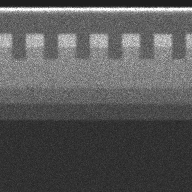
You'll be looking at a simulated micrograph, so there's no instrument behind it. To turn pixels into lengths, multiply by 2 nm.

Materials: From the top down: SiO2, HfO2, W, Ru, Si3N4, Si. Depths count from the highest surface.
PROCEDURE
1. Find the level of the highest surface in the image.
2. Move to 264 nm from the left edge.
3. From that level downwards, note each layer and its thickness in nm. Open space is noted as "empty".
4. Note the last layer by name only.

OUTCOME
SiO2 52, HfO2 26, W 82, Ru 32, Si3N4 32, Si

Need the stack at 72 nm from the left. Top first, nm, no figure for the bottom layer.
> SiO2 52, HfO2 26, W 82, Ru 32, Si3N4 32, Si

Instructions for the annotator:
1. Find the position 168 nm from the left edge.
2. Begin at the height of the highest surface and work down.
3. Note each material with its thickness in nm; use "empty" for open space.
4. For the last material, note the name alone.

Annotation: SiO2 102, W 58, Ru 32, Si3N4 32, Si